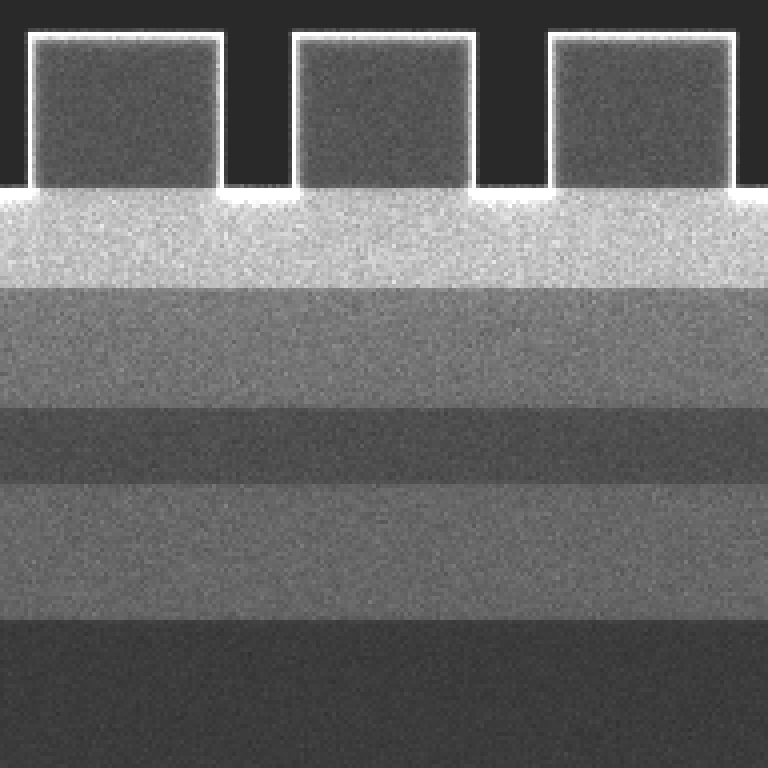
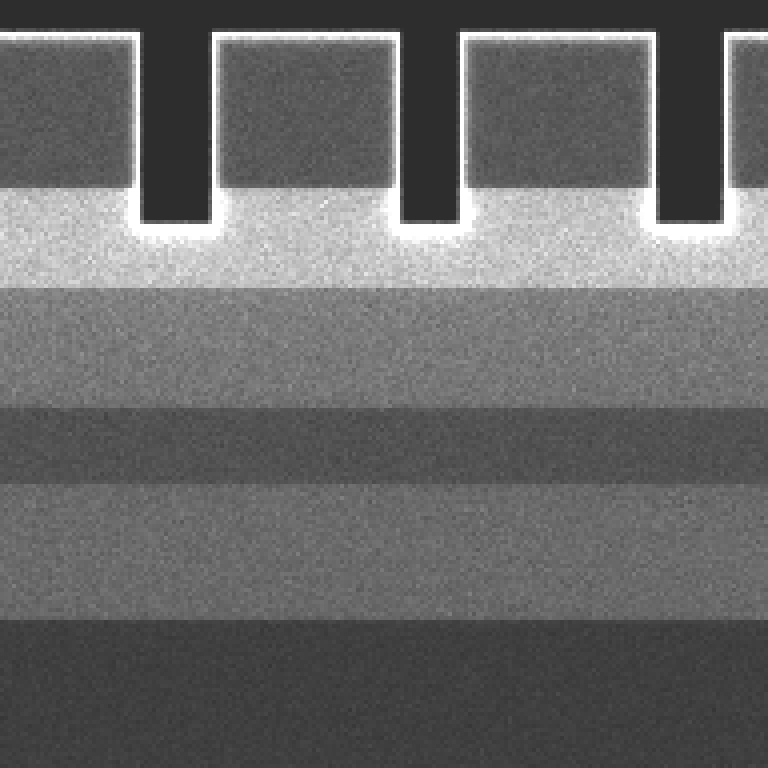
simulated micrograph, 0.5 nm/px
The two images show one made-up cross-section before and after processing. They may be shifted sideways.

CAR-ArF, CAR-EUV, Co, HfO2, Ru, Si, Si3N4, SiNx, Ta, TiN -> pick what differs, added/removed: HfO2 removed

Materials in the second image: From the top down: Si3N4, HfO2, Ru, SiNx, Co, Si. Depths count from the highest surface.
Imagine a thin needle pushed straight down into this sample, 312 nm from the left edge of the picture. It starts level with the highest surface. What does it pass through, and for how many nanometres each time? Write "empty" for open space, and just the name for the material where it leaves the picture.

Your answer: Si3N4 78, HfO2 50, Ru 60, SiNx 38, Co 68, Si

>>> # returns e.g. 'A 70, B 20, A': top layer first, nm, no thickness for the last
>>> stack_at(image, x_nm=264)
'Si3N4 78, HfO2 50, Ru 60, SiNx 38, Co 68, Si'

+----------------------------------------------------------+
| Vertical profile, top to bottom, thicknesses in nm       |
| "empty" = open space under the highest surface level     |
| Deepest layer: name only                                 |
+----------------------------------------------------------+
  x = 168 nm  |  Si3N4 78, HfO2 50, Ru 60, SiNx 38, Co 68, Si